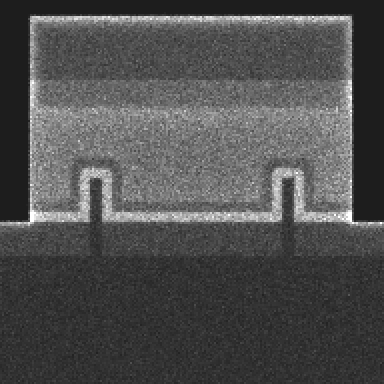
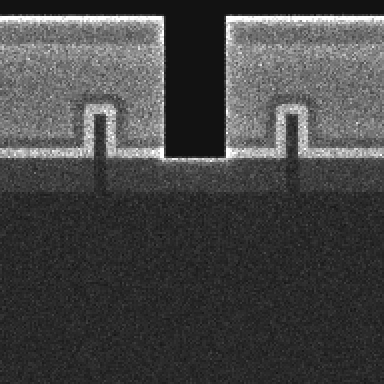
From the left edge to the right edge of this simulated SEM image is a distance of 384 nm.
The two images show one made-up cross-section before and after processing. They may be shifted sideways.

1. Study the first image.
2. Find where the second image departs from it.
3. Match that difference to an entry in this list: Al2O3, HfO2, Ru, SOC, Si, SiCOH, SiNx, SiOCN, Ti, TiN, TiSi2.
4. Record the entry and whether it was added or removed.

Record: SOC / removed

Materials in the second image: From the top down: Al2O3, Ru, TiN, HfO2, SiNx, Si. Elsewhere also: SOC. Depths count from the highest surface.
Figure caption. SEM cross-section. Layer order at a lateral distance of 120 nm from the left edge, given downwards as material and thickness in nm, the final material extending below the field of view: Al2O3 28, Ru 54, TiN 50, HfO2 10, SiNx 34, Si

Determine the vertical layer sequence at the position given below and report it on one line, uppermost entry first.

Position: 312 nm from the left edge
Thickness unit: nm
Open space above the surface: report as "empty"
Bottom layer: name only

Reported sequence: Al2O3 28, Ru 54, TiN 50, HfO2 10, SiNx 34, Si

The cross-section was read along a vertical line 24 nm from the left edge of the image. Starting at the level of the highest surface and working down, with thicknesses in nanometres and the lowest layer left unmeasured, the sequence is Al2O3 28, Ru 94, TiN 10, HfO2 10, SiNx 34, Si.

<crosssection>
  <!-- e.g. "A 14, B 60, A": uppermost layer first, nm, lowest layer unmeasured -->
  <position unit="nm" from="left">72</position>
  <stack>Al2O3 28, Ru 94, TiN 10, HfO2 10, SiNx 34, Si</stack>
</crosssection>